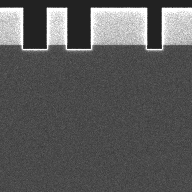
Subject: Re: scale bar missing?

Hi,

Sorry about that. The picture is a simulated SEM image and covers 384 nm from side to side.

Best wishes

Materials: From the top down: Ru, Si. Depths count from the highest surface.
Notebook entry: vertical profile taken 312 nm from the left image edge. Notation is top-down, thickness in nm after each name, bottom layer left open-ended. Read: empty 82, Si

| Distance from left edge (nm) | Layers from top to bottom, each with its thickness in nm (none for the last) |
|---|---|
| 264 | Ru 74, Si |